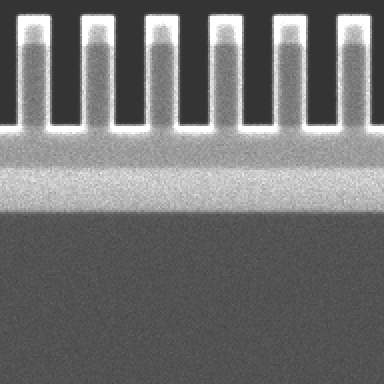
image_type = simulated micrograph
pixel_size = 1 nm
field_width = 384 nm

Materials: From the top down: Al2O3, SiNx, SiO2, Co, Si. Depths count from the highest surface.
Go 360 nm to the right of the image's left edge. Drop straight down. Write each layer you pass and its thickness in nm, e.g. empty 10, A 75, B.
Al2O3 28, SiNx 82, SiO2 42, Co 44, Si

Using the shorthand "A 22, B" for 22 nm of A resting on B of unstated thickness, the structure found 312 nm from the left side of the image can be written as empty 110, SiO2 42, Co 44, Si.